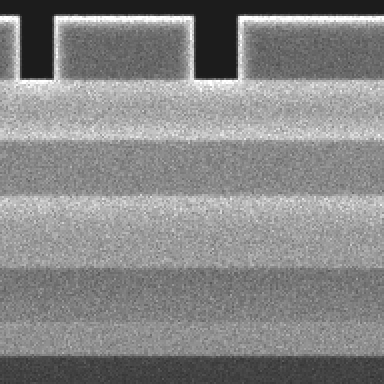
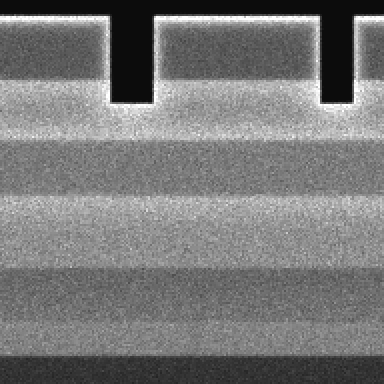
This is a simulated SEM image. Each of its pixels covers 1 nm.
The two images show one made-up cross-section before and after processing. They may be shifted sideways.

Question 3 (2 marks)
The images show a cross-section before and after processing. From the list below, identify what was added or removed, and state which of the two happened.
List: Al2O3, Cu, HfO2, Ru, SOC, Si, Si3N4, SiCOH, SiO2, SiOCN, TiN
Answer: Ru was removed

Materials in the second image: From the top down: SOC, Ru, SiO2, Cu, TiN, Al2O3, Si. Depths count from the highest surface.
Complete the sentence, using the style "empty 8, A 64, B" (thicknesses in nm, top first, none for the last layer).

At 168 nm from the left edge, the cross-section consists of SOC 64, Ru 60, SiO2 56, Cu 72, TiN 54, Al2O3 34, Si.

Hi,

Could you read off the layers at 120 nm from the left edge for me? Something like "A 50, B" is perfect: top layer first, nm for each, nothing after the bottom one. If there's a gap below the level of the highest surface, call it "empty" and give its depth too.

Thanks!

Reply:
empty 88, Ru 36, SiO2 56, Cu 72, TiN 54, Al2O3 34, Si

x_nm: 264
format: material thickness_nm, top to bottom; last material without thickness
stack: SOC 64, Ru 60, SiO2 56, Cu 72, TiN 54, Al2O3 34, Si